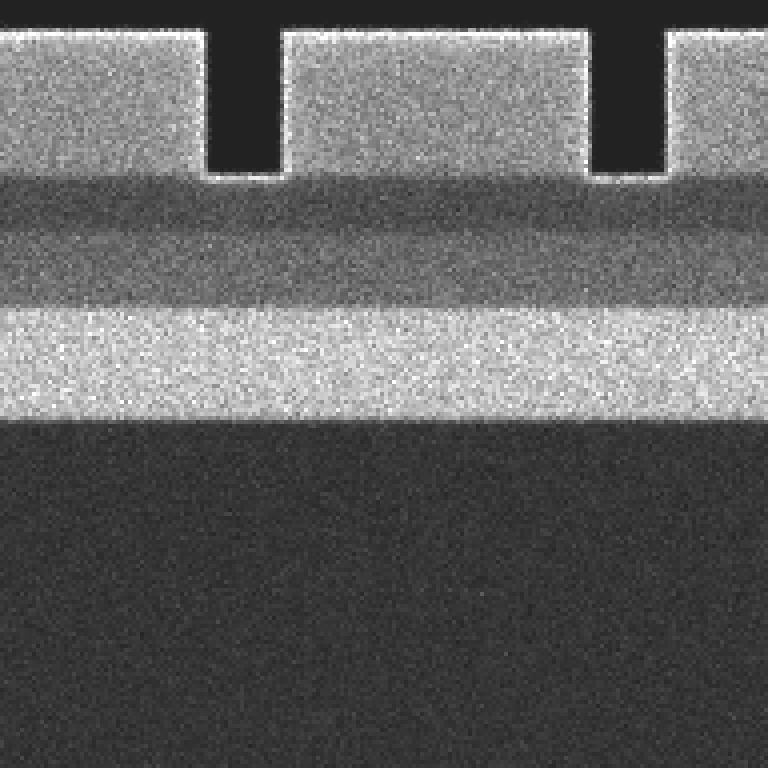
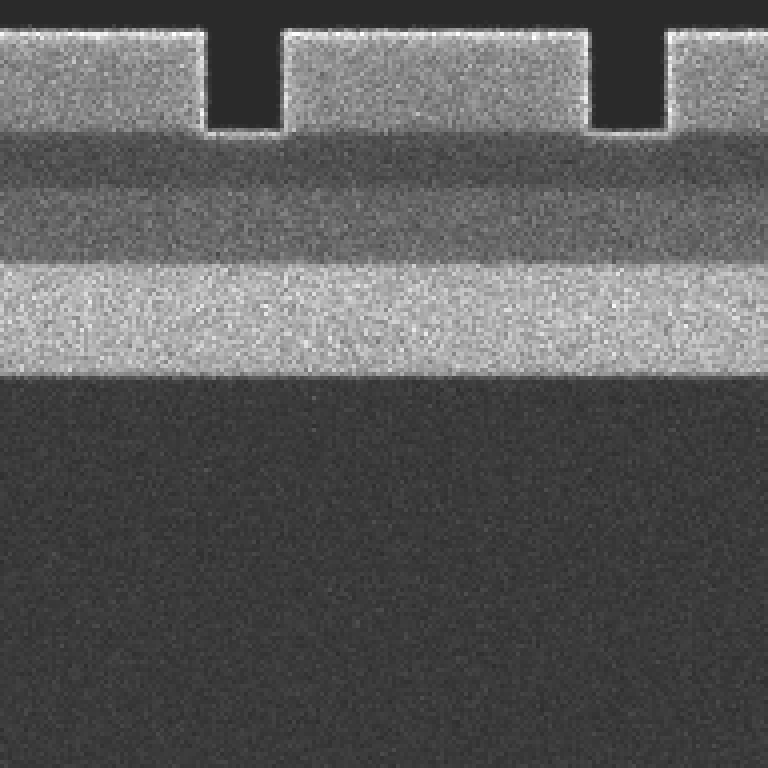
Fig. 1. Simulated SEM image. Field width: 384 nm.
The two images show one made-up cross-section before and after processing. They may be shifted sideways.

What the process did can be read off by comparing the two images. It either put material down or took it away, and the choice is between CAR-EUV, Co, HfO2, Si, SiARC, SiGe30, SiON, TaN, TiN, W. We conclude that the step removed W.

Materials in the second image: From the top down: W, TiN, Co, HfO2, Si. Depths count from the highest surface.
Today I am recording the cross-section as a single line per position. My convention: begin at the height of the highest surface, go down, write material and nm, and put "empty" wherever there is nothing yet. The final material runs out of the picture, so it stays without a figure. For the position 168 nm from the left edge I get W 50, TiN 28, Co 38, HfO2 56, Si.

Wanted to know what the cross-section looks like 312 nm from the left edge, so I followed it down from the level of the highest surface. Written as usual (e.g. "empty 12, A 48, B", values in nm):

empty 50, TiN 28, Co 38, HfO2 56, Si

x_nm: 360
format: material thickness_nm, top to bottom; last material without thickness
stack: W 50, TiN 28, Co 38, HfO2 56, Si